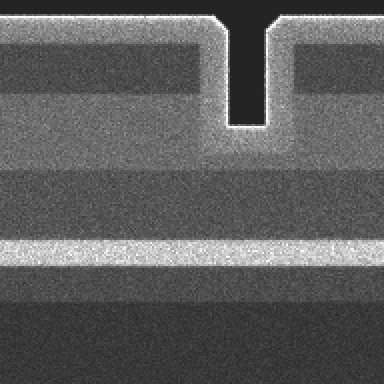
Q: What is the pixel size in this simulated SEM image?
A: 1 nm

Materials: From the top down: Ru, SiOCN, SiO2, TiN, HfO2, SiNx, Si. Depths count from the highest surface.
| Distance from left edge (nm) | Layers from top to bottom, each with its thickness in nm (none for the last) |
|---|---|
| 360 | Ru 28, SiOCN 50, SiO2 76, TiN 70, HfO2 26, SiNx 36, Si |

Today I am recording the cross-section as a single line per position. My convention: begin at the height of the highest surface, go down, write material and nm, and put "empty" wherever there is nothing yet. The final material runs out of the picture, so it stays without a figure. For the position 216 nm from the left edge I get empty 4, Ru 134, SiO2 16, TiN 70, HfO2 26, SiNx 36, Si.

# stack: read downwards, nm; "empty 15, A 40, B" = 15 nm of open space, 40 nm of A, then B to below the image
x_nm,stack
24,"Ru 28, SiOCN 50, SiO2 76, TiN 70, HfO2 26, SiNx 36, Si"